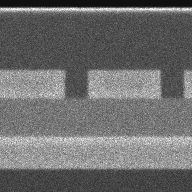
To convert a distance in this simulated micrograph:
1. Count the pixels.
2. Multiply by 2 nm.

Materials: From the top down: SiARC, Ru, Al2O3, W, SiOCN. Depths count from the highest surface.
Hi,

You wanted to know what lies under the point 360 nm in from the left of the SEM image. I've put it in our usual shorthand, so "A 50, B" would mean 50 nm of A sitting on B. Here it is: SiARC 180, Al2O3 78, W 64, SiOCN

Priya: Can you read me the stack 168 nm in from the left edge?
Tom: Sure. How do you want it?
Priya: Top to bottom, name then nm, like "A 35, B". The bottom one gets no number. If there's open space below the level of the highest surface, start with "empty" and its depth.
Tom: SiARC 180, Al2O3 78, W 64, SiOCN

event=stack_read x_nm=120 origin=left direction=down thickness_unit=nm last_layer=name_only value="SiARC 124, Ru 56, Al2O3 78, W 64, SiOCN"